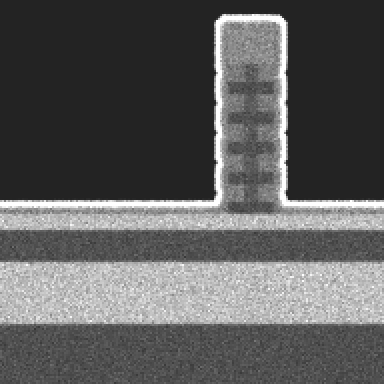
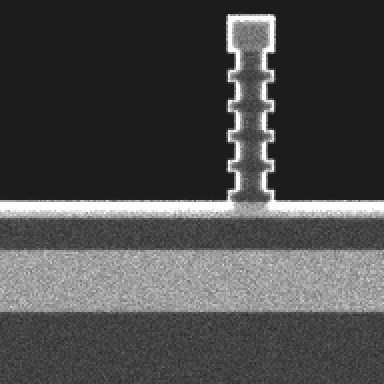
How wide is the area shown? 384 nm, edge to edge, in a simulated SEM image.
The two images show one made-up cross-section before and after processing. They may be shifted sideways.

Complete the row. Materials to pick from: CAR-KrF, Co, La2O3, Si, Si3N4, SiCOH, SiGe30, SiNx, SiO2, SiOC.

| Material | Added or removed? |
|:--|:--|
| SiNx | removed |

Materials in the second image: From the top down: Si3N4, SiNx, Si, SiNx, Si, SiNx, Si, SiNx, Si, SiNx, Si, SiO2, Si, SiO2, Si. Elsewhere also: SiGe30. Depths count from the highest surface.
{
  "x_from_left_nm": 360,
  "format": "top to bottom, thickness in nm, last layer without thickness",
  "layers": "empty 186, SiO2 16, Si 32, SiO2 62, Si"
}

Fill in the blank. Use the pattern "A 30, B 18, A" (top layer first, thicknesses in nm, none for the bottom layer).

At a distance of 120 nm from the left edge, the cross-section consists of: empty 186, SiO2 16, Si 32, SiO2 62, Si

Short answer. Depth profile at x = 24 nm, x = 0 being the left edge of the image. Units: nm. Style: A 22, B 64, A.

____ empty 186, SiO2 16, Si 32, SiO2 62, Si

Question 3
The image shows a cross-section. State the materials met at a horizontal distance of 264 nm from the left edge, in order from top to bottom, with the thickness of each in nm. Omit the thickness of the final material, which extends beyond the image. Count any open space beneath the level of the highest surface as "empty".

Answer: Si3N4 36, SiNx 18, Si 12, SiNx 18, Si 12, SiNx 18, Si 12, SiNx 18, Si 12, SiNx 18, Si 12, SiO2 16, Si 32, SiO2 62, Si